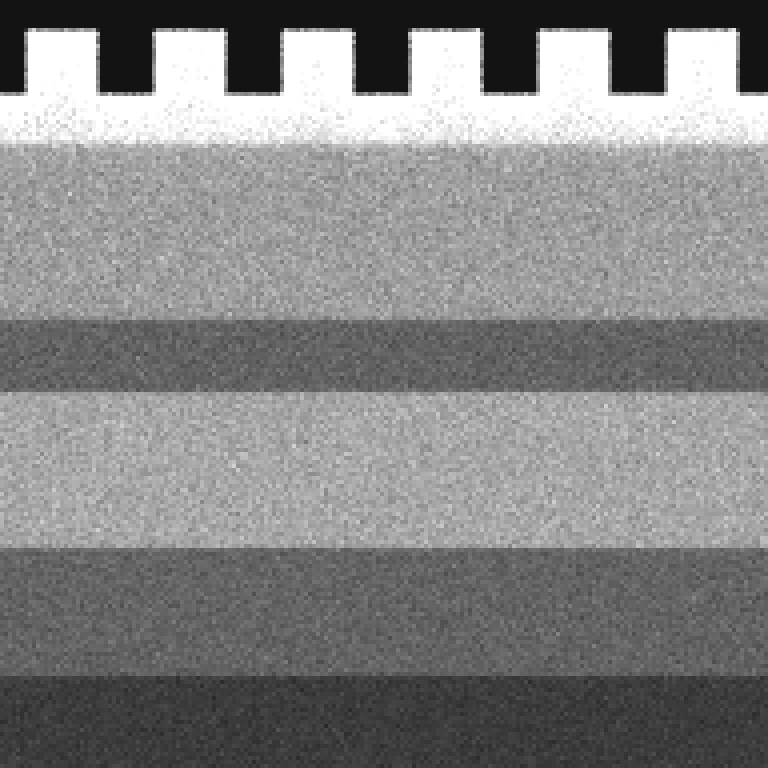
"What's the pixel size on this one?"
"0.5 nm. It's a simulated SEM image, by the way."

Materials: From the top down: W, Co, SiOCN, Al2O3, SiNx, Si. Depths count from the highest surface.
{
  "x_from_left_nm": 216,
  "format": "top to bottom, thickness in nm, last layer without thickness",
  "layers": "W 56, Co 88, SiOCN 36, Al2O3 78, SiNx 64, Si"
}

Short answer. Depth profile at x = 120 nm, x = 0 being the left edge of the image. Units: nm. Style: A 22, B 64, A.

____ empty 32, W 24, Co 88, SiOCN 36, Al2O3 78, SiNx 64, Si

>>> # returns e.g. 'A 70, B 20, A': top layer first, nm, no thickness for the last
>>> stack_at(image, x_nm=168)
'W 56, Co 88, SiOCN 36, Al2O3 78, SiNx 64, Si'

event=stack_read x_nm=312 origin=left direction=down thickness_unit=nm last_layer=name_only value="empty 32, W 24, Co 88, SiOCN 36, Al2O3 78, SiNx 64, Si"